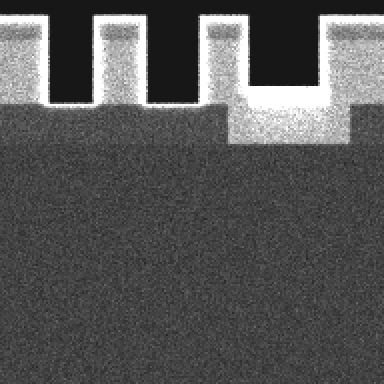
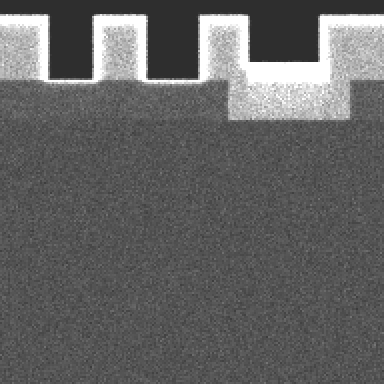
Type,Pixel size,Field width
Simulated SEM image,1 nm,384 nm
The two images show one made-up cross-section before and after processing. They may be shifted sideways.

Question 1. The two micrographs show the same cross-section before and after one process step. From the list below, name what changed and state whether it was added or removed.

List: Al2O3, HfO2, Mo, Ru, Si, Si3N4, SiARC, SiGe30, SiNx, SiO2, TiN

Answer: SiARC, removed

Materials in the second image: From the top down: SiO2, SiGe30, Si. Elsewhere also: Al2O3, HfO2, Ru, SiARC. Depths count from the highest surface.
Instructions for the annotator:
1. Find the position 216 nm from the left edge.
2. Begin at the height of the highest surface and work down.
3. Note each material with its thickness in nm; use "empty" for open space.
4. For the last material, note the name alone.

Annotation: SiO2 64, SiGe30 40, Si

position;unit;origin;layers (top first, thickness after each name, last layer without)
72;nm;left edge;empty 64, SiGe30 40, Si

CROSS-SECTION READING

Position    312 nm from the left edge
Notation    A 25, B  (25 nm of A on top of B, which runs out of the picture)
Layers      empty 48, HfO2 18, Ru 38, Si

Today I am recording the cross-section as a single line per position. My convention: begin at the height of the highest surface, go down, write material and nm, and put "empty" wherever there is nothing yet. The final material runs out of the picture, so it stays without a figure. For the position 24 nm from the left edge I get SiO2 64, SiGe30 40, Si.